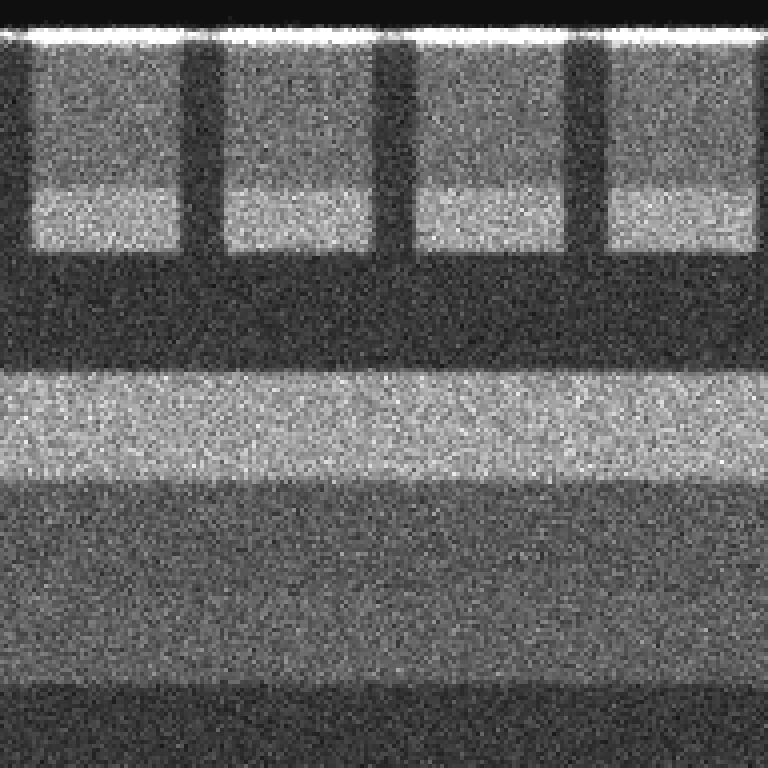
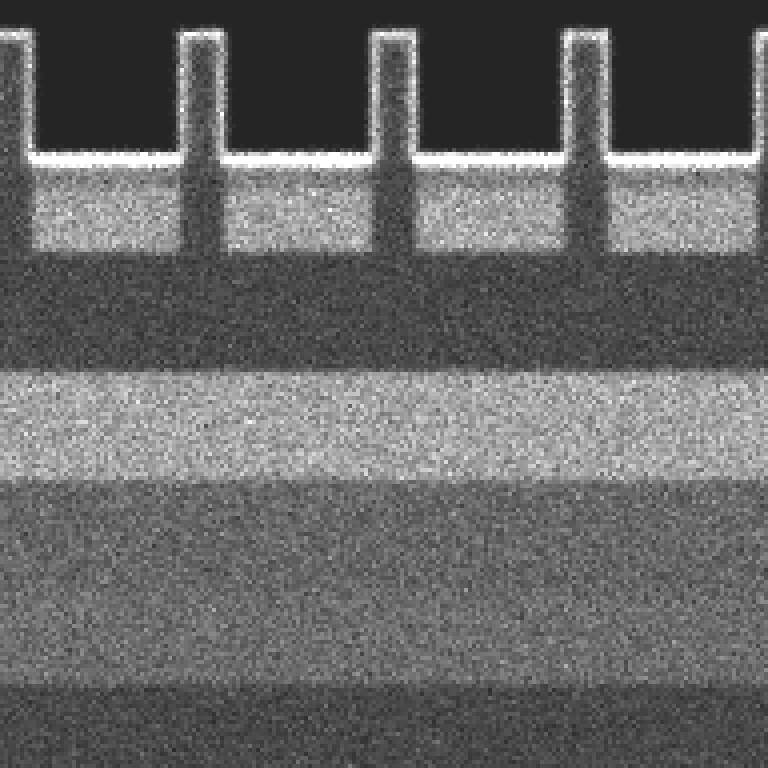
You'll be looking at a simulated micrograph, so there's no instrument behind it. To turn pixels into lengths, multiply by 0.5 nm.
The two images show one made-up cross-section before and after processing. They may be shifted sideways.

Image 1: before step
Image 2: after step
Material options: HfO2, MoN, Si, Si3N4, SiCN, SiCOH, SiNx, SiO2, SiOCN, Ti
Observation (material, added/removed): Si3N4, removed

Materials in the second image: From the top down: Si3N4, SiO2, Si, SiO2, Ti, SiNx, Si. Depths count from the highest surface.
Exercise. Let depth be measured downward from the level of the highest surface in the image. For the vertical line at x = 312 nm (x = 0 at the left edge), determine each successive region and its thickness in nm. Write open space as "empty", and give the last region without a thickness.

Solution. empty 62, Si3N4 16, SiO2 32, Si 60, SiO2 54, Ti 56, SiNx 46, Si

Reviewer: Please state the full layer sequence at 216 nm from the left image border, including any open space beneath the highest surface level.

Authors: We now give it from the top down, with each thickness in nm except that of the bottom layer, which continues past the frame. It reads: empty 62, Si3N4 16, SiO2 32, Si 60, SiO2 54, Ti 56, SiNx 46, Si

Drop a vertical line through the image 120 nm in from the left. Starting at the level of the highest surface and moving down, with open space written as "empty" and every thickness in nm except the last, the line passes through empty 62, Si3N4 16, SiO2 32, Si 60, SiO2 54, Ti 56, SiNx 46, Si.